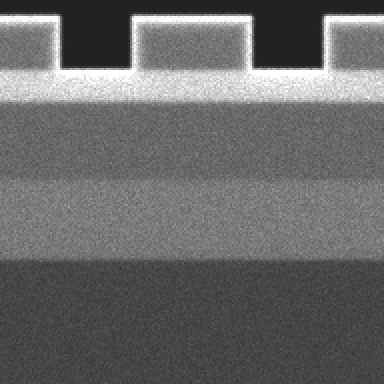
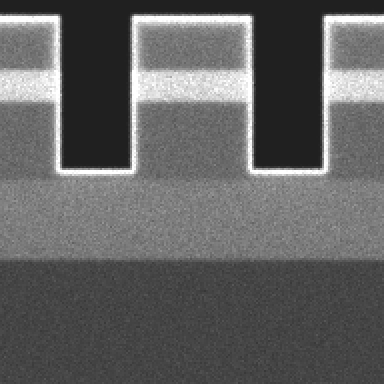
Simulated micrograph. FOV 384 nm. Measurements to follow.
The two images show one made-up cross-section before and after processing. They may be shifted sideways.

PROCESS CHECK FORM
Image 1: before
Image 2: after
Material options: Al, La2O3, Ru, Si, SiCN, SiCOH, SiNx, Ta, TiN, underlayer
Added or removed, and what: removed, Ru and SiNx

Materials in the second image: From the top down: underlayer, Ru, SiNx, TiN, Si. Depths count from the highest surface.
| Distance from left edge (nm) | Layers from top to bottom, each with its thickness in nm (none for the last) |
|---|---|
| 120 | empty 154, SiNx 10, TiN 80, Si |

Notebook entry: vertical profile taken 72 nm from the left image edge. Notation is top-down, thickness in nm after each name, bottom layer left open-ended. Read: empty 154, SiNx 10, TiN 80, Si